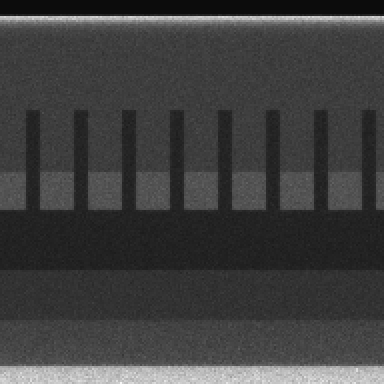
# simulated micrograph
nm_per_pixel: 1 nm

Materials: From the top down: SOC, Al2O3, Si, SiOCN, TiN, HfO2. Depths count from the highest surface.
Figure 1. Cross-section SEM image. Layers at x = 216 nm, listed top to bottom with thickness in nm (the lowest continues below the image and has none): SOC 156, Al2O3 38, Si 60, SiOCN 50, TiN 46, HfO2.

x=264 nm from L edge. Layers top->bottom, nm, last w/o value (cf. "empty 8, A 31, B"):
SOC 156, Al2O3 38, Si 60, SiOCN 50, TiN 46, HfO2